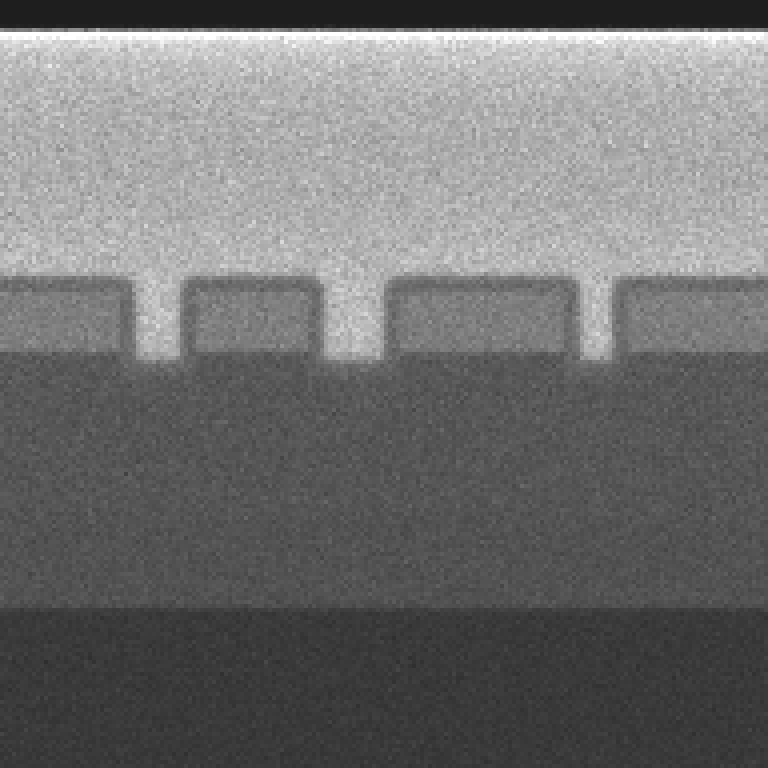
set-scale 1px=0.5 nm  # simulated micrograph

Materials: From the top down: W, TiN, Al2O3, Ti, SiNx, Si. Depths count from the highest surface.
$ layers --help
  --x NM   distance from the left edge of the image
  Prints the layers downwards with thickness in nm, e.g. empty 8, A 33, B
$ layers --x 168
W 164, TiN 8, Ti 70, SiNx 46, Si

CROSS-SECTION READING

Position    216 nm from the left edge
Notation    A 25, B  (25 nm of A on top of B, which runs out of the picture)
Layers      W 122, TiN 8, Al2O3 30, Ti 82, SiNx 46, Si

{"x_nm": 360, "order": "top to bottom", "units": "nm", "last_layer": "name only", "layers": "W 122, TiN 8, Al2O3 30, Ti 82, SiNx 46, Si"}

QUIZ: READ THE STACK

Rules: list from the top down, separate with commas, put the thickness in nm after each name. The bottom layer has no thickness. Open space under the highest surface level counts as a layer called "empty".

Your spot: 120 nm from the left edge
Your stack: W 122, TiN 8, Al2O3 30, Ti 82, SiNx 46, Si